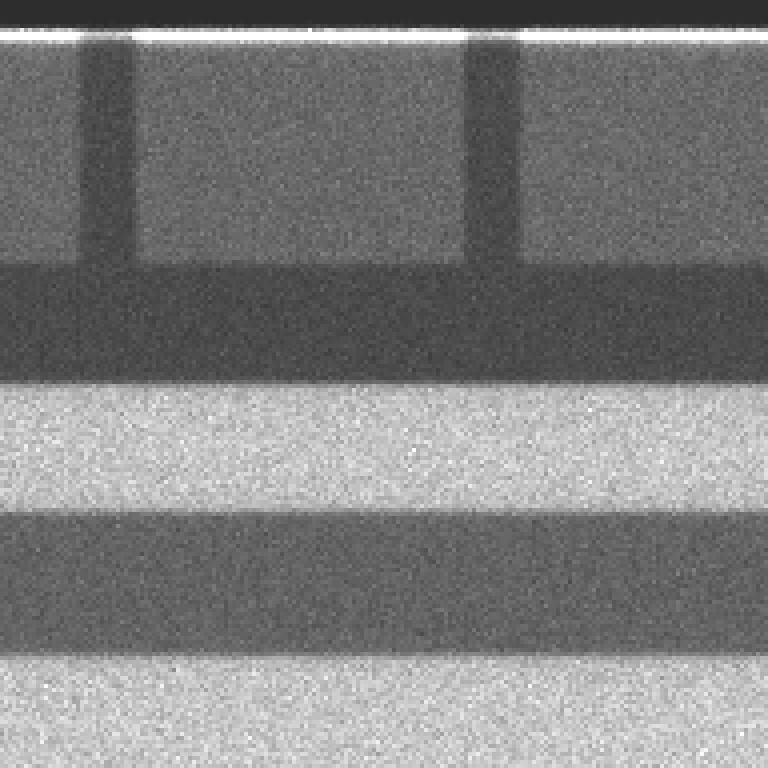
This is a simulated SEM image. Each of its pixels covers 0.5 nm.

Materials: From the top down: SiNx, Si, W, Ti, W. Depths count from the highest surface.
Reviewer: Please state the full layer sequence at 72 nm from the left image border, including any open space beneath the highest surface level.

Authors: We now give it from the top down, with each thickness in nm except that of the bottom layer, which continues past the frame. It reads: SiNx 116, Si 60, W 64, Ti 72, W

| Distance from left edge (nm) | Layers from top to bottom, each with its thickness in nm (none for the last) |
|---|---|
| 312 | SiNx 116, Si 60, W 64, Ti 72, W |